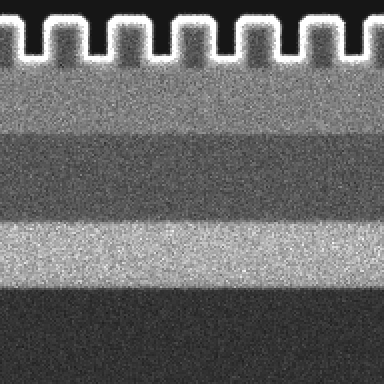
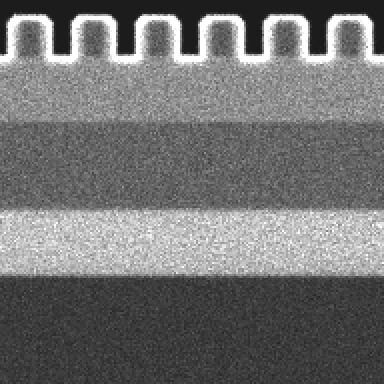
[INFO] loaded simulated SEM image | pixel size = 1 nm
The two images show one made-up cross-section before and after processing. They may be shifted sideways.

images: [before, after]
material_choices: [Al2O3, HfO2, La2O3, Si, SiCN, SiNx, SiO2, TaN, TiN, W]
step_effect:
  removed: SiO2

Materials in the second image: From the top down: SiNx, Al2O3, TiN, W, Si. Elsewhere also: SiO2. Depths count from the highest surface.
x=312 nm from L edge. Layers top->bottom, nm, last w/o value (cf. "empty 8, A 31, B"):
empty 40, Al2O3 66, TiN 88, W 66, Si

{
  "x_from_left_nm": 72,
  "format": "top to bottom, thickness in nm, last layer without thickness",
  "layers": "empty 6, SiO2 34, Al2O3 66, TiN 88, W 66, Si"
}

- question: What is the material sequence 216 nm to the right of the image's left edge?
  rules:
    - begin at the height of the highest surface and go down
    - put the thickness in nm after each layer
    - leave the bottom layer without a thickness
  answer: SiNx 40, Al2O3 66, TiN 88, W 66, Si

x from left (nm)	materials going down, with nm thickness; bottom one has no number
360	SiO2 40, Al2O3 66, TiN 88, W 66, Si